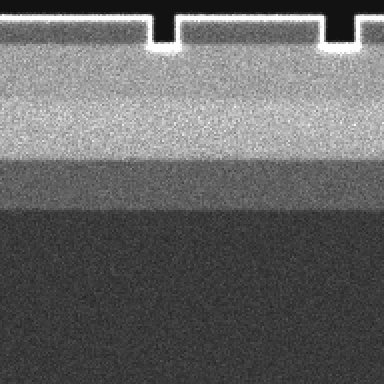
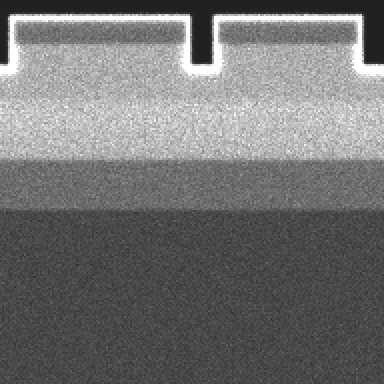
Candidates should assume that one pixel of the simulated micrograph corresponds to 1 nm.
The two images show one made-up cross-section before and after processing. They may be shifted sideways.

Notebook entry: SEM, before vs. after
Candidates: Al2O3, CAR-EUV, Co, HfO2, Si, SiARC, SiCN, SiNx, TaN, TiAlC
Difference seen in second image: Al2O3 removed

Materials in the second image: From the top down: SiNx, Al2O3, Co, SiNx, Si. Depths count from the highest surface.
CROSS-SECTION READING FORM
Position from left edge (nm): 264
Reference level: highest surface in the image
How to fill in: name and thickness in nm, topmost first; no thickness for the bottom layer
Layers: SiNx 28, Al2O3 56, Co 60, SiNx 50, Si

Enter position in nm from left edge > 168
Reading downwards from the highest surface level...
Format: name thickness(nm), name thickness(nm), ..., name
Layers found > SiNx 28, Al2O3 56, Co 60, SiNx 50, Si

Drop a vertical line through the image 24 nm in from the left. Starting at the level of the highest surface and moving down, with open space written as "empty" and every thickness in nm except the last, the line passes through SiNx 28, Al2O3 56, Co 60, SiNx 50, Si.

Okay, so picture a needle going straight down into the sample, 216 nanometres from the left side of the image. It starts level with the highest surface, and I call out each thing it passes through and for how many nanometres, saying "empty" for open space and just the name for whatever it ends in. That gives SiNx 28, Al2O3 56, Co 60, SiNx 50, Si